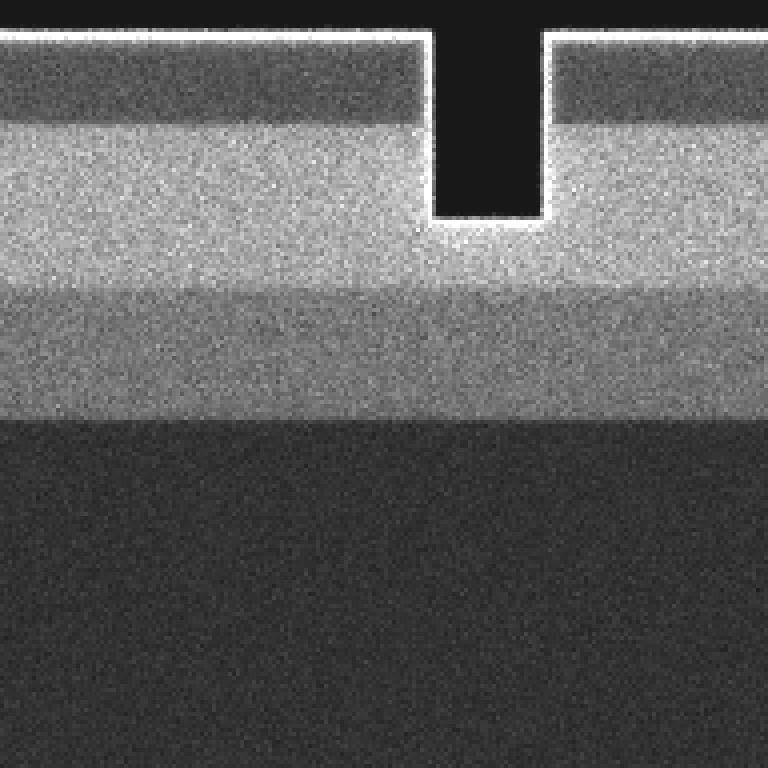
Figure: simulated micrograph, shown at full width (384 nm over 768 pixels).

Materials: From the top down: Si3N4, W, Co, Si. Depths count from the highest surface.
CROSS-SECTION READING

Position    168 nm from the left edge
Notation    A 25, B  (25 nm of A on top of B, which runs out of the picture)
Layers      Si3N4 46, W 82, Co 66, Si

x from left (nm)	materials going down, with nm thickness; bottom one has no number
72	Si3N4 46, W 82, Co 66, Si